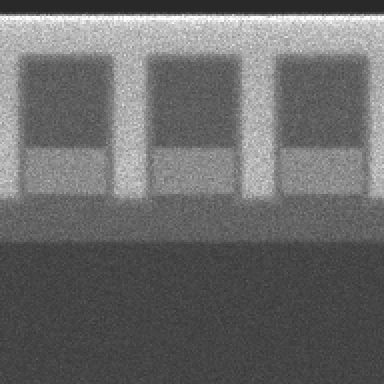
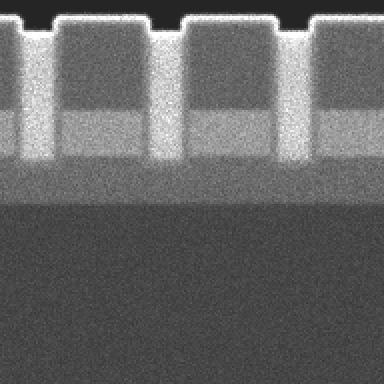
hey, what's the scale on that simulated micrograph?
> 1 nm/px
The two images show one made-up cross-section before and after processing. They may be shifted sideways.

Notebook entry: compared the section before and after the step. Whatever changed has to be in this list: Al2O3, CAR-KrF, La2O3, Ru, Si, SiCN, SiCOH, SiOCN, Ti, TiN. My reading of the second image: Ru removed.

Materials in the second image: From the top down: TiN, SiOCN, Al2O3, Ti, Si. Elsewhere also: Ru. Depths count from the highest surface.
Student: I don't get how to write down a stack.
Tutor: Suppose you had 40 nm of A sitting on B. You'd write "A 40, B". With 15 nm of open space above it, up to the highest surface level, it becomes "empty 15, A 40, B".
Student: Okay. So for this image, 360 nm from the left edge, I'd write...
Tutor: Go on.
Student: TiN 8, SiOCN 86, Al2O3 46, Ti 48, Si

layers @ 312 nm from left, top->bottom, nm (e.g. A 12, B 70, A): empty 2, TiN 150, Ti 36, Si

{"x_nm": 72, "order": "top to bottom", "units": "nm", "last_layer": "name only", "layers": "TiN 8, SiOCN 86, Al2O3 46, Ti 48, Si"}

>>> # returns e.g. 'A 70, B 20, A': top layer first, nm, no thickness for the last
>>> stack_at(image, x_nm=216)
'TiN 8, SiOCN 86, Al2O3 46, Ti 48, Si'